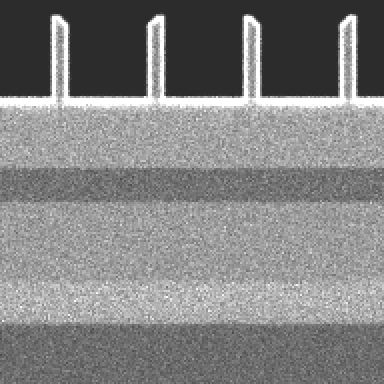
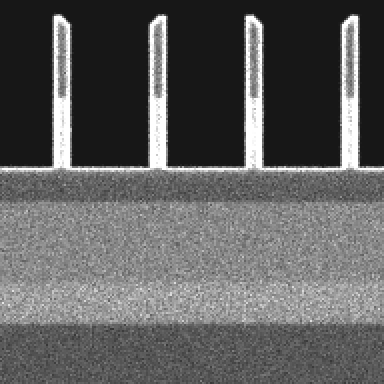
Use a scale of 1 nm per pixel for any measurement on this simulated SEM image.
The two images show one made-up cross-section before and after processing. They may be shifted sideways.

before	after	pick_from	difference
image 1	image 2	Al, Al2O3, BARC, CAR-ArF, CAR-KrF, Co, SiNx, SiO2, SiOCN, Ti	Al2O3 removed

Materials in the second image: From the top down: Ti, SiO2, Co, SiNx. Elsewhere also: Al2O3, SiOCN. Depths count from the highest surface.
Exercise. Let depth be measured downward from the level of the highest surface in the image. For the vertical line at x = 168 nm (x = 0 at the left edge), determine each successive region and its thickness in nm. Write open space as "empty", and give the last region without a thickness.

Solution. empty 152, Ti 34, SiO2 80, Co 42, SiNx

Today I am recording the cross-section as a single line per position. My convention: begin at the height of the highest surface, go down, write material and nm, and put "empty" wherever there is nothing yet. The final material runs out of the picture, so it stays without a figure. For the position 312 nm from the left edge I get empty 152, Ti 34, SiO2 80, Co 42, SiNx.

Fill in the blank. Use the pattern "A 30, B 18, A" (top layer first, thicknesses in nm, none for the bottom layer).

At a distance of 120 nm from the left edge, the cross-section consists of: empty 152, Ti 34, SiO2 80, Co 42, SiNx